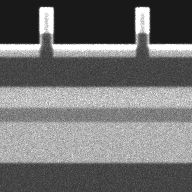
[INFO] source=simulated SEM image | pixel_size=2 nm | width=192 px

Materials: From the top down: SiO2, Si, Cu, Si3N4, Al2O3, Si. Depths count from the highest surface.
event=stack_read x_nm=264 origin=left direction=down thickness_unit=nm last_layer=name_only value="empty 74, SiO2 24, Si 60, Cu 42, Si3N4 28, Al2O3 82, Si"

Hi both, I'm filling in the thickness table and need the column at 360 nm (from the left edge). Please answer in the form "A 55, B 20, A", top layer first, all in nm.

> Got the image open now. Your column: empty 74, SiO2 24, Si 60, Cu 42, Si3N4 28, Al2O3 82, Si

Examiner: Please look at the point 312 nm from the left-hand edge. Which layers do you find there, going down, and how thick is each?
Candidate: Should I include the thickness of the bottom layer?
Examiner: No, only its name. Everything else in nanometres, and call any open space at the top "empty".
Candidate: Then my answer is empty 74, SiO2 24, Si 60, Cu 42, Si3N4 28, Al2O3 82, Si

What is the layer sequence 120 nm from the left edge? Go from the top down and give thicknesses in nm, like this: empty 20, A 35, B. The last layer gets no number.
empty 74, SiO2 24, Si 60, Cu 42, Si3N4 28, Al2O3 82, Si